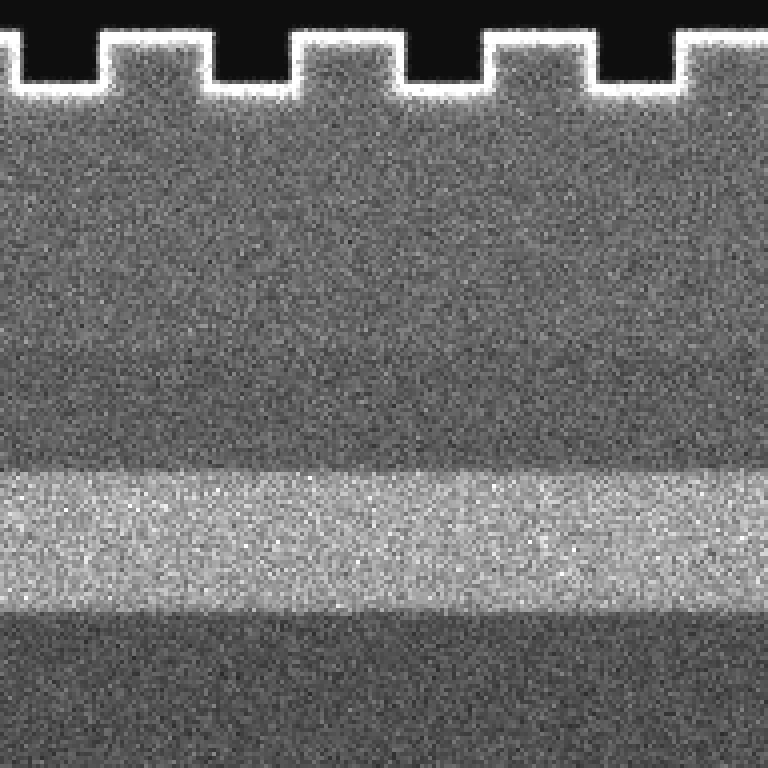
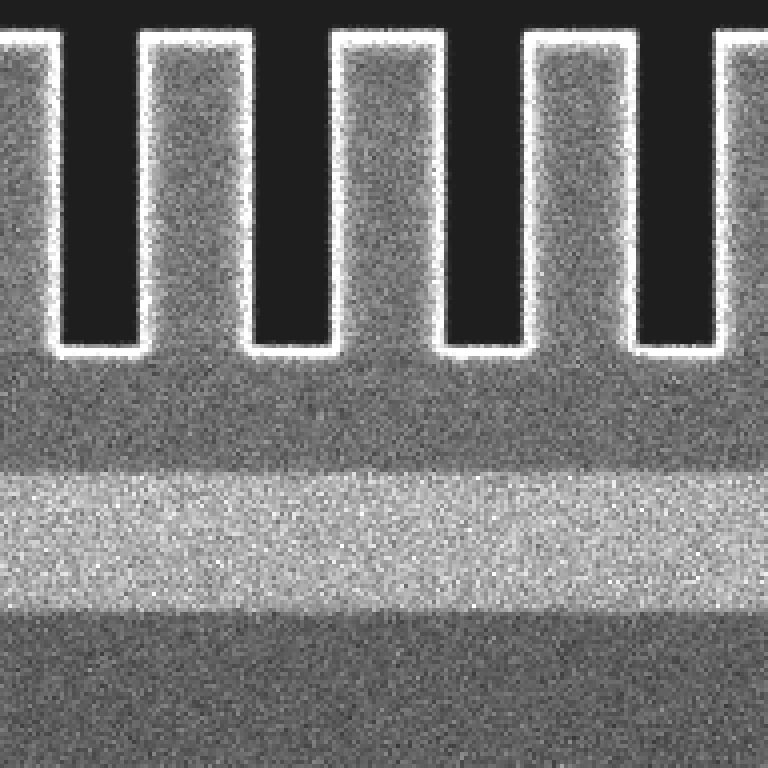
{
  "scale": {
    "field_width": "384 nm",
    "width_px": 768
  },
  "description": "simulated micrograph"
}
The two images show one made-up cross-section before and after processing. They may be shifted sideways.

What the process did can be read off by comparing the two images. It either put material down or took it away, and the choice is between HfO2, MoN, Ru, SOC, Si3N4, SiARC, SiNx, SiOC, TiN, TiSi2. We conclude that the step removed SOC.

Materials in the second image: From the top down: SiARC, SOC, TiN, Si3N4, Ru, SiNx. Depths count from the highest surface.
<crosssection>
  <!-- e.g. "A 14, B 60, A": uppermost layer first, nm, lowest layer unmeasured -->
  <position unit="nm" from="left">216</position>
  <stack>SiARC 26, SOC 132, Si3N4 62, Ru 70, SiNx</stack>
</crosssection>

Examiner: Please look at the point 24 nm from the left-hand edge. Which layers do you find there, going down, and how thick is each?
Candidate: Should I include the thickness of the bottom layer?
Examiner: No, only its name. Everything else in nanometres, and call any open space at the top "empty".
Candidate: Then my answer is SiARC 26, SOC 132, Si3N4 62, Ru 70, SiNx